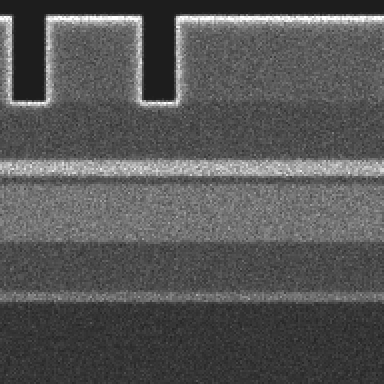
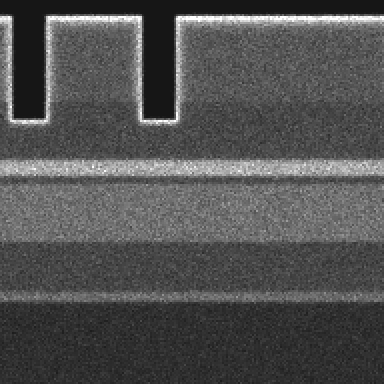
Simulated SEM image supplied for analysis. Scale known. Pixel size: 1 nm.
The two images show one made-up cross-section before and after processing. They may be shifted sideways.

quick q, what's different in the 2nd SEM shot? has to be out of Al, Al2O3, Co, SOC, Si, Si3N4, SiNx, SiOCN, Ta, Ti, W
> SiNx removed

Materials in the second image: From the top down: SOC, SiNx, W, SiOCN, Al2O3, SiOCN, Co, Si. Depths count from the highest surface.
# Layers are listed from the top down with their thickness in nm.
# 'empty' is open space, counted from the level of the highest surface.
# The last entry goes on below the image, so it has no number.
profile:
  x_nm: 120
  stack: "SOC 86, SiNx 58, W 16, SiOCN 8, Al2O3 58, SiOCN 50, Co 10, Si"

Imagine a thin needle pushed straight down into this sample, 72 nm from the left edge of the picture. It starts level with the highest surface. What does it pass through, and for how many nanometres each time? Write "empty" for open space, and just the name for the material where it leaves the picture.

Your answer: SOC 86, SiNx 58, W 16, SiOCN 8, Al2O3 58, SiOCN 50, Co 10, Si